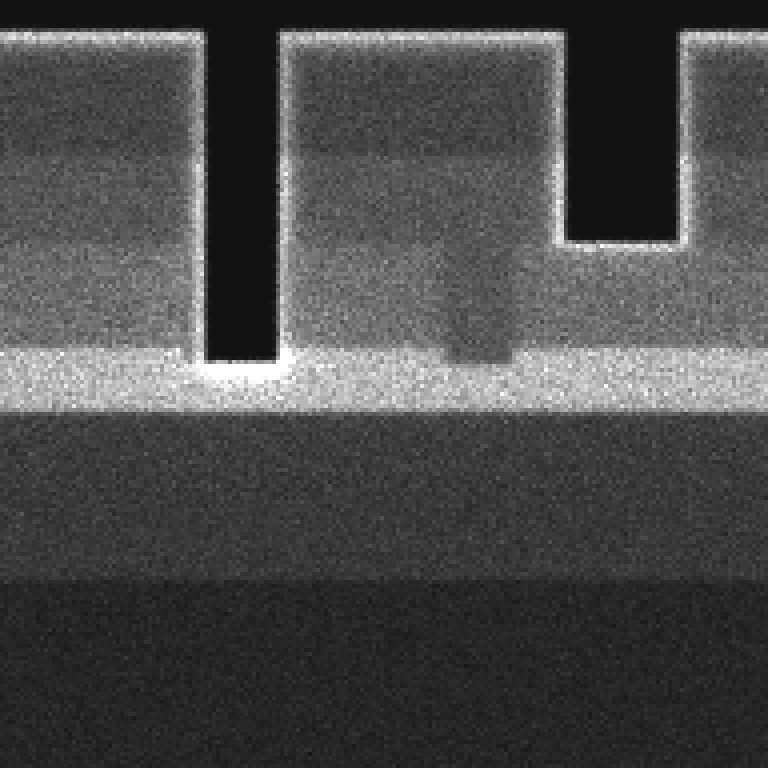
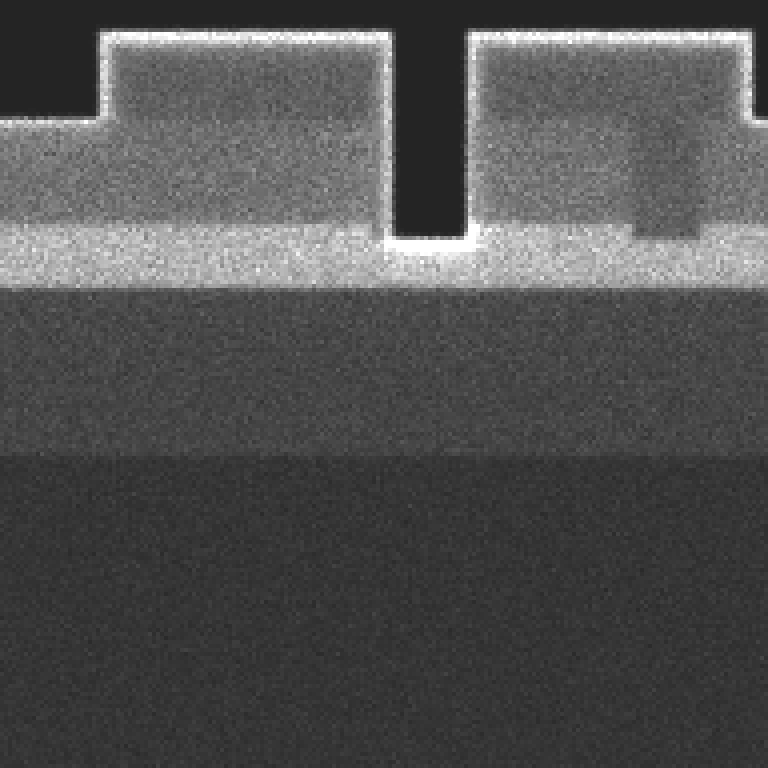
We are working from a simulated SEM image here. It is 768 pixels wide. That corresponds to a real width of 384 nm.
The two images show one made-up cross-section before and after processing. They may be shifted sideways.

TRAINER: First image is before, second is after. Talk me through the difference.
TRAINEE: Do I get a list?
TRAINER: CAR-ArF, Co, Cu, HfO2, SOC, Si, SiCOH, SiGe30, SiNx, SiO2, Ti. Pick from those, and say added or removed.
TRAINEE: removed: SOC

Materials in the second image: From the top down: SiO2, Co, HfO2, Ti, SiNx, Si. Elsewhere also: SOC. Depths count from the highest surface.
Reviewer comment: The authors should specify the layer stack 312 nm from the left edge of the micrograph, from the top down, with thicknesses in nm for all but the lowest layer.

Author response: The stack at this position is SiO2 44, Co 52, HfO2 32, Ti 42, SiNx 42, Si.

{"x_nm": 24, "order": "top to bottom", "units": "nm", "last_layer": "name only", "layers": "empty 44, Co 52, HfO2 32, Ti 42, SiNx 42, Si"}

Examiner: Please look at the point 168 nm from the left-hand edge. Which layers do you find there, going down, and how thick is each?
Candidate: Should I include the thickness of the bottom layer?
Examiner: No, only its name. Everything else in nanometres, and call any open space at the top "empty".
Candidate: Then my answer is SiO2 44, Co 52, HfO2 32, Ti 42, SiNx 42, Si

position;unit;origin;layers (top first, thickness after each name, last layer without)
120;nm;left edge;SiO2 44, Co 52, HfO2 32, Ti 42, SiNx 42, Si